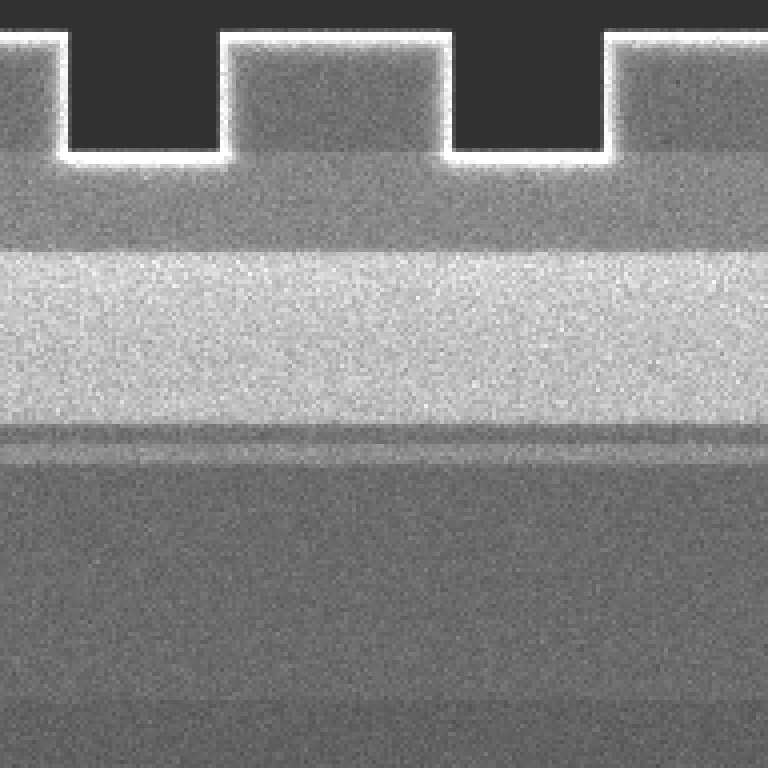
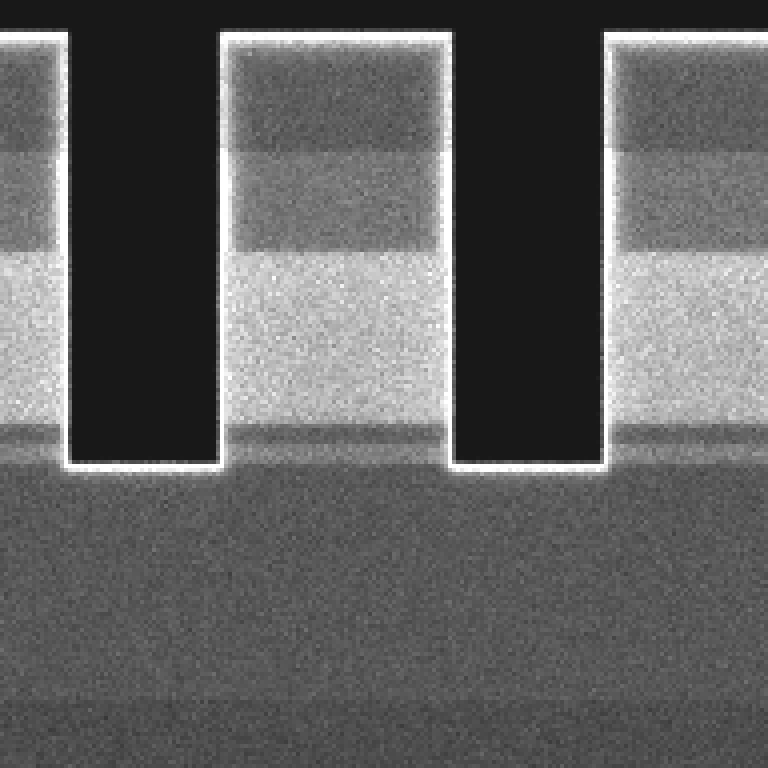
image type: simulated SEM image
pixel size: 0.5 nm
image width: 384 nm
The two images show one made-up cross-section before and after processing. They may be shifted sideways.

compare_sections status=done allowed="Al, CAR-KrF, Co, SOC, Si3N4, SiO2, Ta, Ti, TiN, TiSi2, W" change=removed material="Co and SiO2 and TiN and W"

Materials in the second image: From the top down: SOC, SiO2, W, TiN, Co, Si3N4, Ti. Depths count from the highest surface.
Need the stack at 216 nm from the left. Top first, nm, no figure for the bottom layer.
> SOC 60, SiO2 50, W 86, TiN 10, Co 10, Si3N4 118, Ti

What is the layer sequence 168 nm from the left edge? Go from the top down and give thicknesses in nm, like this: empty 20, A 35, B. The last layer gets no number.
SOC 60, SiO2 50, W 86, TiN 10, Co 10, Si3N4 118, Ti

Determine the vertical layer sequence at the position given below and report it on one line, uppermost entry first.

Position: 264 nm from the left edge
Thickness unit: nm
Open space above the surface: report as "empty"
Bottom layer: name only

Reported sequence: empty 216, Si3N4 118, Ti